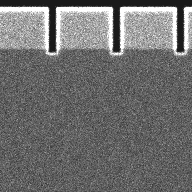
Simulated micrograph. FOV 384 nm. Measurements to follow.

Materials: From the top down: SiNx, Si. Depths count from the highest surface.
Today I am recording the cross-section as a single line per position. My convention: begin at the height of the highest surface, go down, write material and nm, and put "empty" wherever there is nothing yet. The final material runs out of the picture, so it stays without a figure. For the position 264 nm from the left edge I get SiNx 82, Si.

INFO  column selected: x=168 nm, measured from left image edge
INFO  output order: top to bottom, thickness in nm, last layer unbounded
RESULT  SiNx 82, Si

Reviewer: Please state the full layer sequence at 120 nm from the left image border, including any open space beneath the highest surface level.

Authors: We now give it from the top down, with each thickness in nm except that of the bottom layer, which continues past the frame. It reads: SiNx 82, Si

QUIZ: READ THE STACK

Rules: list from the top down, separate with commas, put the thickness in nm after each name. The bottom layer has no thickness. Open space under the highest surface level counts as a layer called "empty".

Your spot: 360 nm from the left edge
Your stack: empty 90, Si